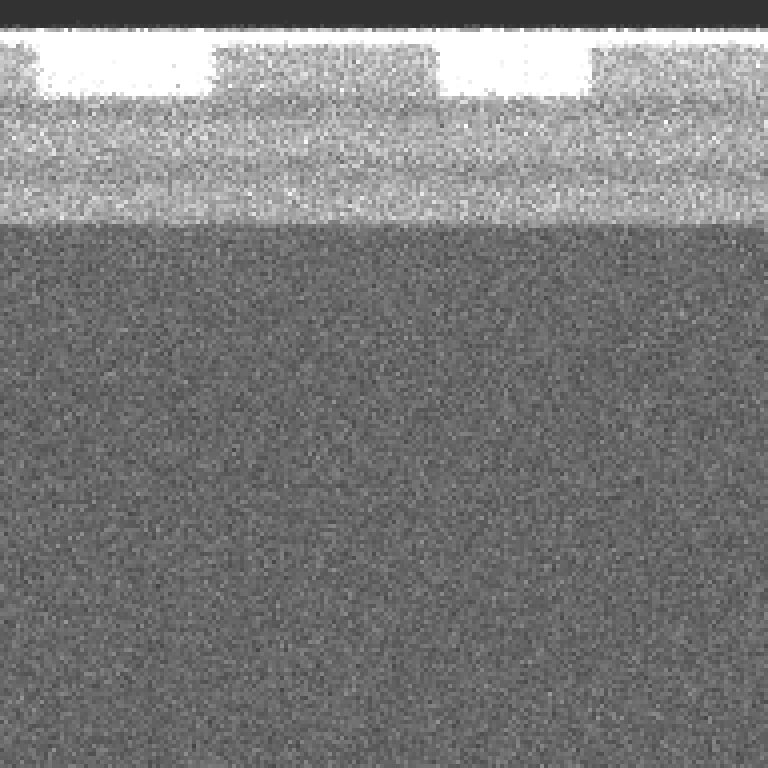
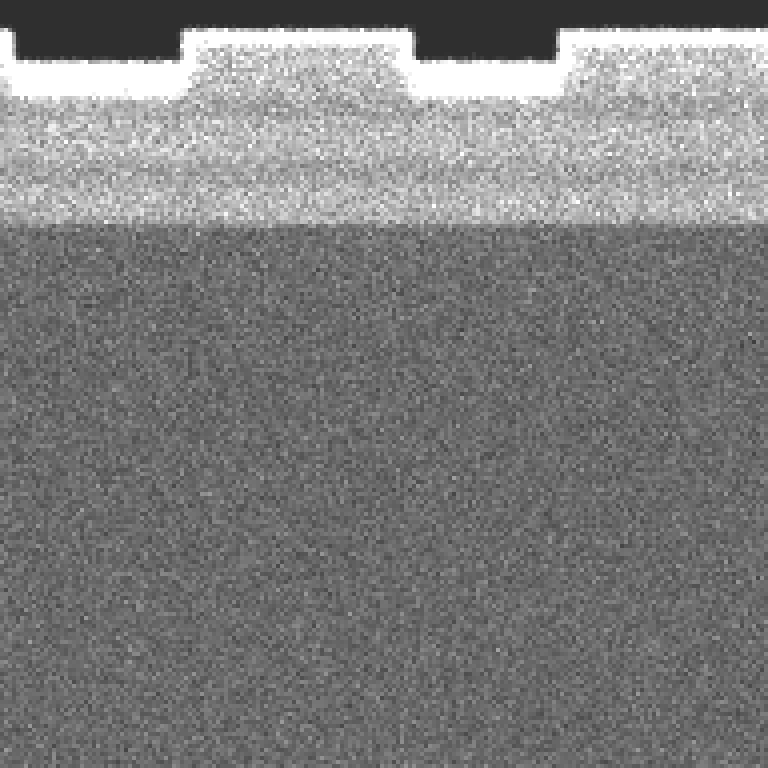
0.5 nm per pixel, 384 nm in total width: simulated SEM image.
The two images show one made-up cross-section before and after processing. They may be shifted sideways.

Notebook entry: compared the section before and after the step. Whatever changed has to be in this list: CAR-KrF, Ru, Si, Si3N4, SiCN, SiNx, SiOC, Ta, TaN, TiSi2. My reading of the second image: Ru removed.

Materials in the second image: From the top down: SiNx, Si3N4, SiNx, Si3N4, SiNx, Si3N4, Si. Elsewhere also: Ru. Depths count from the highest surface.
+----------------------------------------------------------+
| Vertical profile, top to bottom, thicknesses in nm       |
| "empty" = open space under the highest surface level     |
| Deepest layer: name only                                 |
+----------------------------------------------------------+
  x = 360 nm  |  SiNx 12, Si3N4 20, SiNx 12, Si3N4 20, SiNx 12, Si3N4 20, Si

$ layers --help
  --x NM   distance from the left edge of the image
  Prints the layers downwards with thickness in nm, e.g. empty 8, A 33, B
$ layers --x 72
empty 16, Ru 16, SiNx 12, Si3N4 20, SiNx 12, Si3N4 20, Si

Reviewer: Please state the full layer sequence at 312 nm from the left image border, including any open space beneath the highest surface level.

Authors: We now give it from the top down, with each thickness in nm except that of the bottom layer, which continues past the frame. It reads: SiNx 12, Si3N4 20, SiNx 12, Si3N4 20, SiNx 12, Si3N4 20, Si